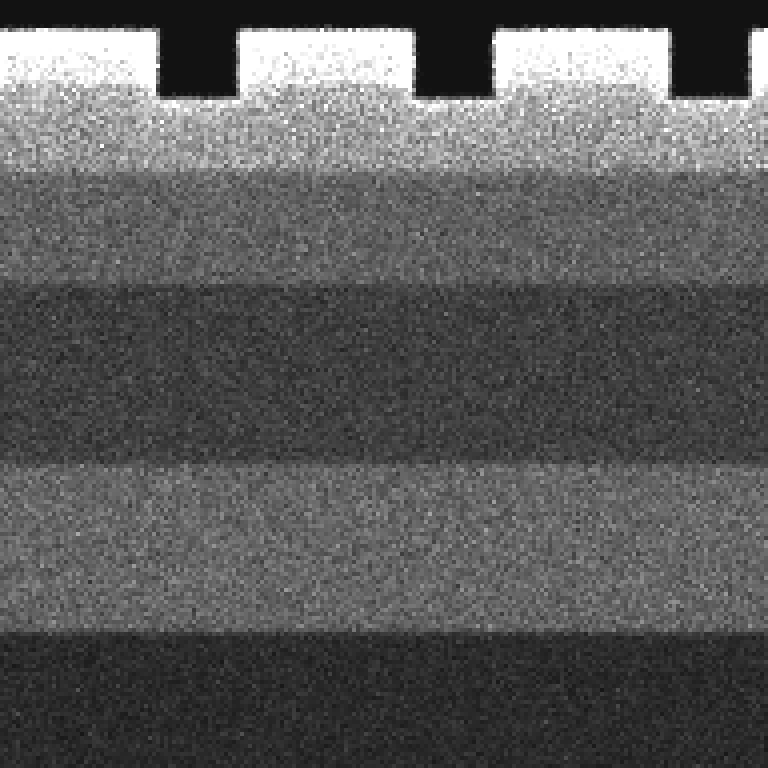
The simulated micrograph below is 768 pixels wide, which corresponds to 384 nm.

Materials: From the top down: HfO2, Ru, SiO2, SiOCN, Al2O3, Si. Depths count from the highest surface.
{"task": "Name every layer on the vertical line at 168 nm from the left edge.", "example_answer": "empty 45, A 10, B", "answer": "HfO2 26, Ru 44, SiO2 56, SiOCN 90, Al2O3 84, Si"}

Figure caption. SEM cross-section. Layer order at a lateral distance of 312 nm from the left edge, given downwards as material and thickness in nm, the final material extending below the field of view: HfO2 26, Ru 44, SiO2 56, SiOCN 90, Al2O3 84, Si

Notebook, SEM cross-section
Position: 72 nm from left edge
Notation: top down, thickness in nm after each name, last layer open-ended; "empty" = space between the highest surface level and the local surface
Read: HfO2 26, Ru 44, SiO2 56, SiOCN 90, Al2O3 84, Si